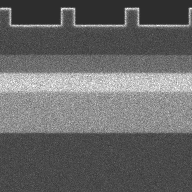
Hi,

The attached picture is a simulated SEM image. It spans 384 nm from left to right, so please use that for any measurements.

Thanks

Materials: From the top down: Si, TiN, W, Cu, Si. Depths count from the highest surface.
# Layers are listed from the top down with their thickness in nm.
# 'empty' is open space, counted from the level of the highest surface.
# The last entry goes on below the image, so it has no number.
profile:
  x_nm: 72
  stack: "empty 34, Si 60, TiN 36, W 38, Cu 82, Si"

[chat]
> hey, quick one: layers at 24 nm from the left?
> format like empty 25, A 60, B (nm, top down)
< empty 34, Si 60, TiN 36, W 38, Cu 82, Si